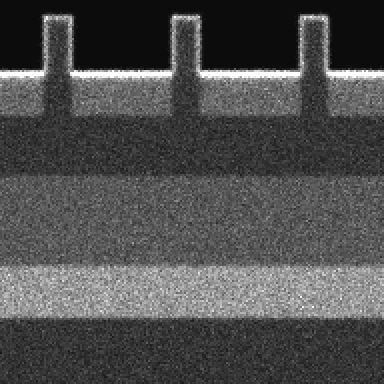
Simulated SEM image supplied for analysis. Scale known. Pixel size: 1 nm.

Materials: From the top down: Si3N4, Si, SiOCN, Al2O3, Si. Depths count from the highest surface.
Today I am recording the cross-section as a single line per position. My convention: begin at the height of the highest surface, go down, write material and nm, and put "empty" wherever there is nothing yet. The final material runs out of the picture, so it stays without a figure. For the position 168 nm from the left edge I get empty 56, Si3N4 44, Si 60, SiOCN 90, Al2O3 52, Si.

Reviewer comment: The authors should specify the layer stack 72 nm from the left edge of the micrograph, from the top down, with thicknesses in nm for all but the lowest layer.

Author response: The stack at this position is empty 56, Si3N4 44, Si 60, SiOCN 90, Al2O3 52, Si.